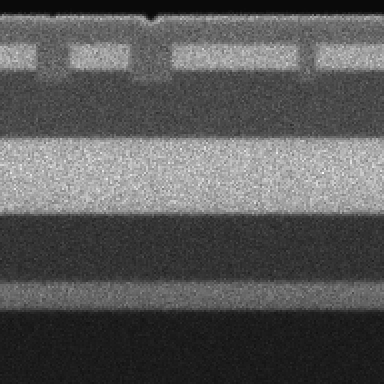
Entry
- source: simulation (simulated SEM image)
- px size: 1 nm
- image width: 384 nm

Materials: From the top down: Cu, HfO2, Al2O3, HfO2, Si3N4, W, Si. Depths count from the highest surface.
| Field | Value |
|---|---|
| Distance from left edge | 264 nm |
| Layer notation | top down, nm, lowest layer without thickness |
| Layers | Cu 28, HfO2 26, Al2O3 68, HfO2 76, Si3N4 68, W 28, Si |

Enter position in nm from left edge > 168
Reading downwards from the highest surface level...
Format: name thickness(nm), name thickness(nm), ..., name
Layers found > Cu 66, Al2O3 56, HfO2 76, Si3N4 68, W 28, Si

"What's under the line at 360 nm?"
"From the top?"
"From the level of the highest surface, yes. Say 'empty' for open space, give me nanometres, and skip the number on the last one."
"Cu 28, HfO2 26, Al2O3 68, HfO2 76, Si3N4 68, W 28, Si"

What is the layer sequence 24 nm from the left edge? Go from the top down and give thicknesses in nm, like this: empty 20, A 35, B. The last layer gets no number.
Cu 28, HfO2 26, Al2O3 68, HfO2 76, Si3N4 68, W 28, Si